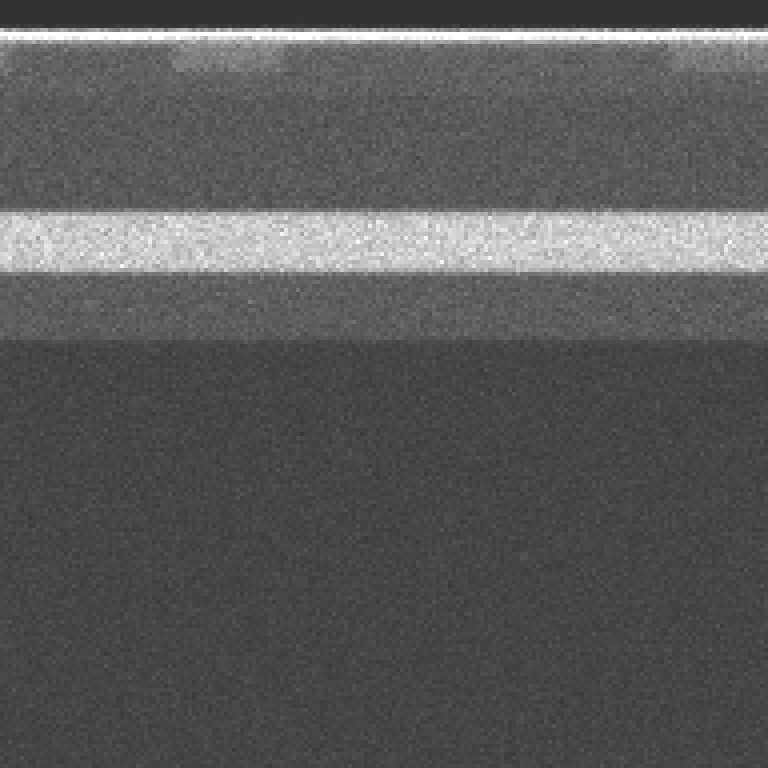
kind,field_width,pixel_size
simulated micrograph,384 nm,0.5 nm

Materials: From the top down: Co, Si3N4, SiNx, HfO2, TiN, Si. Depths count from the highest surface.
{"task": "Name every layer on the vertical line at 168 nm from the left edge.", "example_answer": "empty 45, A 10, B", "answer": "Si3N4 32, SiNx 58, HfO2 30, TiN 34, Si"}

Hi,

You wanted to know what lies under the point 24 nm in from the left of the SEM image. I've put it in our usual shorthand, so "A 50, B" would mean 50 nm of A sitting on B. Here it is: Si3N4 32, SiNx 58, HfO2 30, TiN 34, Si